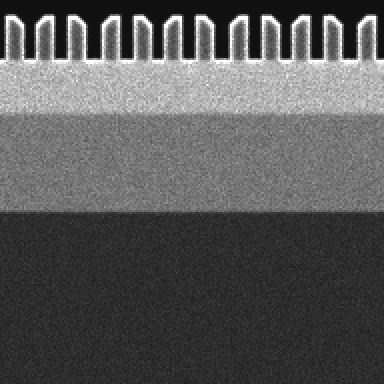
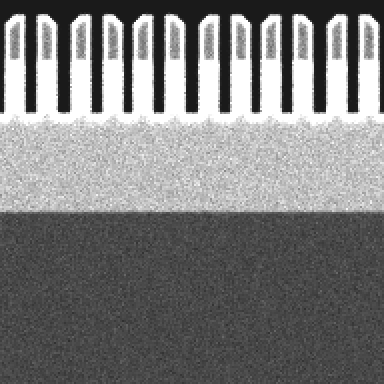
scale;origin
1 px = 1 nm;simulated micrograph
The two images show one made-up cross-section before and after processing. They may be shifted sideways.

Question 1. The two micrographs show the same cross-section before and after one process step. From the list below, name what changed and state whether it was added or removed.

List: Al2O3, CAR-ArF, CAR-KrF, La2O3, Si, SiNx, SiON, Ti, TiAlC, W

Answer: W, removed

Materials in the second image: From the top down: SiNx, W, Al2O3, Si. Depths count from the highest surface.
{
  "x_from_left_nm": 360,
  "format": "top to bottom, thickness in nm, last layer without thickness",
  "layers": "SiNx 44, W 54, Al2O3 98, Si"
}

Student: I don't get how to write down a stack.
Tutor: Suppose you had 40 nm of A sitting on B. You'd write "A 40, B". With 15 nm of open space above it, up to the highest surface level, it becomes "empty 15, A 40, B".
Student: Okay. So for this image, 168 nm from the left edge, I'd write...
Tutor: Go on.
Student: SiNx 44, W 54, Al2O3 98, Si